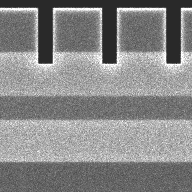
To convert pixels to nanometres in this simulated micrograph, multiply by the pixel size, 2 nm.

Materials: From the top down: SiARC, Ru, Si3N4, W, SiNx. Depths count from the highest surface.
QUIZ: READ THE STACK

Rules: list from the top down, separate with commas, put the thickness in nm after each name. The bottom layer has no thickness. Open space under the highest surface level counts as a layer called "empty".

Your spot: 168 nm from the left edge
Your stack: SiARC 88, Ru 88, Si3N4 48, W 84, SiNx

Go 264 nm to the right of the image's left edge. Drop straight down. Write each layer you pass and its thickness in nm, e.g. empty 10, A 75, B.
SiARC 88, Ru 88, Si3N4 48, W 84, SiNx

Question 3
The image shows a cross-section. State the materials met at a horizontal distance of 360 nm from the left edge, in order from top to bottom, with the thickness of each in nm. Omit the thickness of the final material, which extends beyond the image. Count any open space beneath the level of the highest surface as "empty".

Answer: empty 112, Ru 64, Si3N4 48, W 84, SiNx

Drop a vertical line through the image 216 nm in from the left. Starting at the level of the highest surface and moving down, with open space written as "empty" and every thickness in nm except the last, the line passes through empty 112, Ru 64, Si3N4 48, W 84, SiNx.